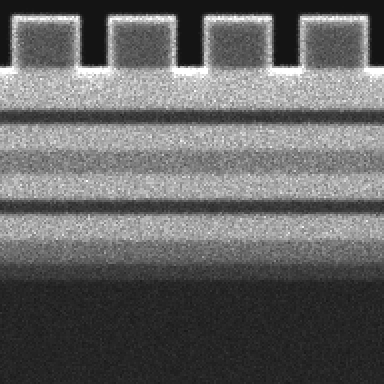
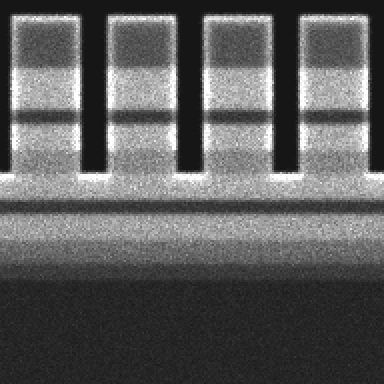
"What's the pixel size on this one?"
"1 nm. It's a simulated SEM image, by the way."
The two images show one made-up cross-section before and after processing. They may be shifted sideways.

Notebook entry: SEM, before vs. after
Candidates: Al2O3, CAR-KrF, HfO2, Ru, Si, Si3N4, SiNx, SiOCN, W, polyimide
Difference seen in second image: HfO2 and Ru and SiOCN removed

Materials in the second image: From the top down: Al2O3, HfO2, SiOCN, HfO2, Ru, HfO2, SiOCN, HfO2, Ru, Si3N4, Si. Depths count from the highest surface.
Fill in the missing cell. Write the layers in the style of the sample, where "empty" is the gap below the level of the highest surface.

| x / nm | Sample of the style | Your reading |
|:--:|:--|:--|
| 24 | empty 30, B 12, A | Al2O3 52, HfO2 42, SiOCN 14, HfO2 26, Ru 24, HfO2 26, SiOCN 14, HfO2 26, Ru 24, Si3N4 16, Si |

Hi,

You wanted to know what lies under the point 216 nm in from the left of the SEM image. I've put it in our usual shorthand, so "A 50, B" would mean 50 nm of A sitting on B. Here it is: Al2O3 52, HfO2 42, SiOCN 14, HfO2 26, Ru 24, HfO2 26, SiOCN 14, HfO2 26, Ru 24, Si3N4 16, Si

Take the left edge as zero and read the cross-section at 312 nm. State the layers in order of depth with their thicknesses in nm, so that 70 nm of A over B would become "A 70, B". Al2O3 52, HfO2 42, SiOCN 14, HfO2 26, Ru 24, HfO2 26, SiOCN 14, HfO2 26, Ru 24, Si3N4 16, Si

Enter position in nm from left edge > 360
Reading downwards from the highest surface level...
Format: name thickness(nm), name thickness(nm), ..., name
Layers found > Al2O3 52, HfO2 42, SiOCN 14, HfO2 26, Ru 24, HfO2 26, SiOCN 14, HfO2 26, Ru 24, Si3N4 16, Si